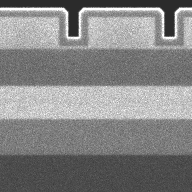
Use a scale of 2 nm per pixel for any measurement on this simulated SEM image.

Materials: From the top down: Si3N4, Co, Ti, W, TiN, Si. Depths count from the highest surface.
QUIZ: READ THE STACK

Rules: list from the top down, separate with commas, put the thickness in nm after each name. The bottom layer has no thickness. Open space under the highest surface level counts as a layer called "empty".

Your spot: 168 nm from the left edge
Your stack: Si3N4 76, Co 6, Ti 74, W 66, TiN 72, Si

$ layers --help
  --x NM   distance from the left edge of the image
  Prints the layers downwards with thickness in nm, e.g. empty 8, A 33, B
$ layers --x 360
Si3N4 76, Co 6, Ti 74, W 66, TiN 72, Si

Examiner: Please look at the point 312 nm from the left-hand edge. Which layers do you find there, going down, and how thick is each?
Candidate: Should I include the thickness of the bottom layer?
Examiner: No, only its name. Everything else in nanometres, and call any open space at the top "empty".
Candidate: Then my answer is Si3N4 76, Co 6, Ti 74, W 66, TiN 72, Si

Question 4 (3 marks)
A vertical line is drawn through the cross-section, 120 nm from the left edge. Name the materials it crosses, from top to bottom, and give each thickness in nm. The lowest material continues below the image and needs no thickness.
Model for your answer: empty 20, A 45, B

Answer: Si3N4 76, Co 6, Ti 74, W 66, TiN 72, Si